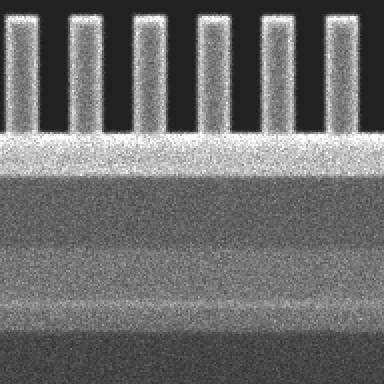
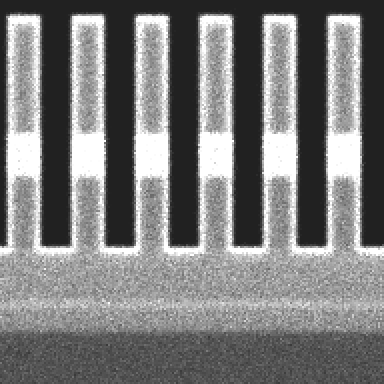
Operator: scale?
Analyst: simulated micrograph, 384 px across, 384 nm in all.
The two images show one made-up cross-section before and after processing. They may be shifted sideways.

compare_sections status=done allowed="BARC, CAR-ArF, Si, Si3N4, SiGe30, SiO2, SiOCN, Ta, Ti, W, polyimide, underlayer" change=removed material="SiOCN and W"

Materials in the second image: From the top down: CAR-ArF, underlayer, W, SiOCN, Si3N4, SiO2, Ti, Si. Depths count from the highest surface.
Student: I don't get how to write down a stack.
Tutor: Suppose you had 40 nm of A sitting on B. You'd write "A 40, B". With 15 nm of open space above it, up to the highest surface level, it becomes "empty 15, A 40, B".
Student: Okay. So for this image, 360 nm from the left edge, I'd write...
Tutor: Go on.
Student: empty 232, Si3N4 52, SiO2 8, Ti 24, Si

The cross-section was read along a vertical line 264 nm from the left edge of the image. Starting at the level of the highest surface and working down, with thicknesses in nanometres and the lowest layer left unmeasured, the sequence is CAR-ArF 68, underlayer 50, W 42, SiOCN 72, Si3N4 52, SiO2 8, Ti 24, Si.